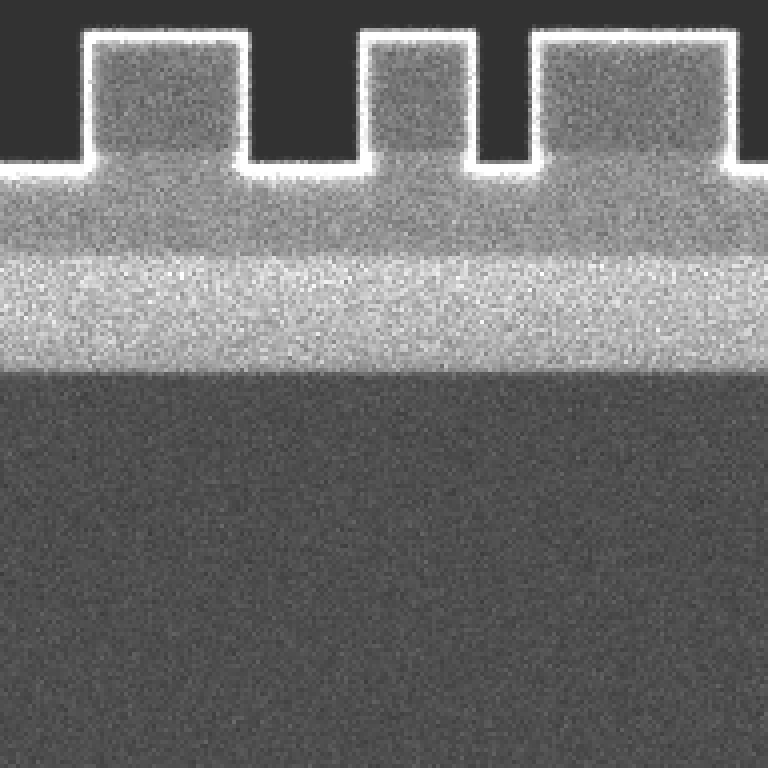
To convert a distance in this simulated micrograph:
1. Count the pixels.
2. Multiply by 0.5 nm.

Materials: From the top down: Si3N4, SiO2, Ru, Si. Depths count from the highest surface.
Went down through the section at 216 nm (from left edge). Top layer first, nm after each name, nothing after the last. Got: Si3N4 60, SiO2 52, Ru 58, Si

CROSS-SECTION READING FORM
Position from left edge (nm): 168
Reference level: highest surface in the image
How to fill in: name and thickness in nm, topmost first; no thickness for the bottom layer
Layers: empty 66, SiO2 46, Ru 58, Si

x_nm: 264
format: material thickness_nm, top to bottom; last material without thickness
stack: empty 66, SiO2 46, Ru 58, Si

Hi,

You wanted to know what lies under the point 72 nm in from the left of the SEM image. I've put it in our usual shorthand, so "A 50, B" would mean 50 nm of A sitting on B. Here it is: Si3N4 60, SiO2 52, Ru 58, Si